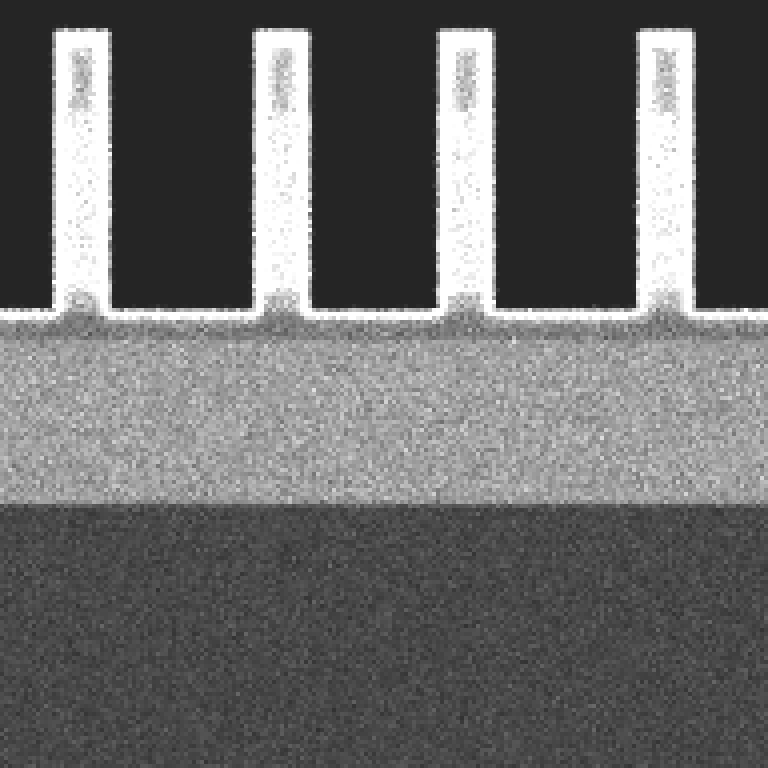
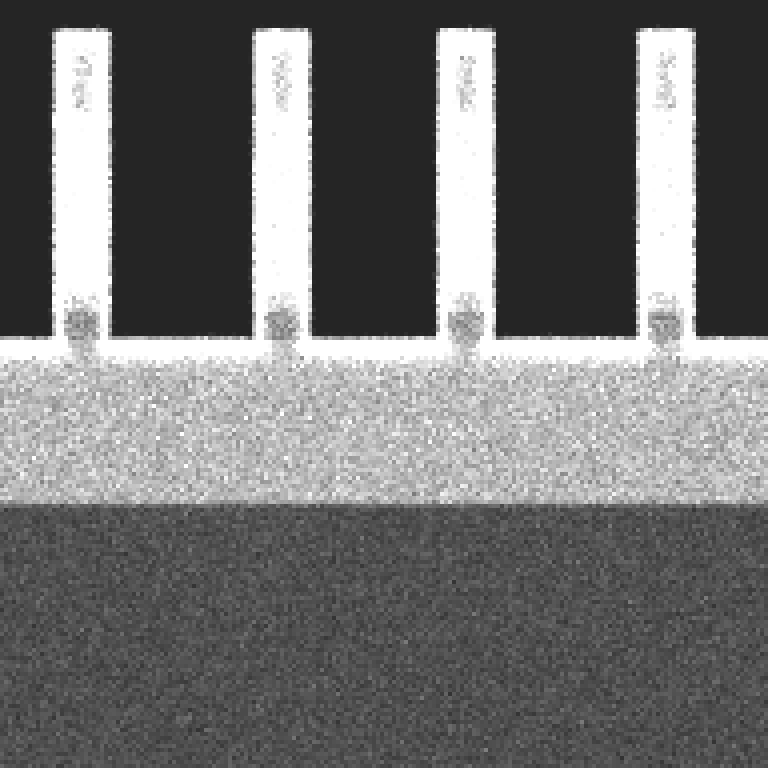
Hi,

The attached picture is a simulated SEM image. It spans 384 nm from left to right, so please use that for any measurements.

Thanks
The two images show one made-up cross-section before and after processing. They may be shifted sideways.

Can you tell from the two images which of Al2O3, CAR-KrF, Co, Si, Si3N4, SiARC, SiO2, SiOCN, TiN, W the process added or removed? Yes, it removed TiN.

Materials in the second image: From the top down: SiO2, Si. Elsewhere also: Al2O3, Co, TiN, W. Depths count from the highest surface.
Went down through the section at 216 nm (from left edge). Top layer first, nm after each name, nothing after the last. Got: empty 154, SiO2 82, Si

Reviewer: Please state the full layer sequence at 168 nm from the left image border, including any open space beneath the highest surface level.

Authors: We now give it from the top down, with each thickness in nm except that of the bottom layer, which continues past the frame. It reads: empty 154, SiO2 82, Si